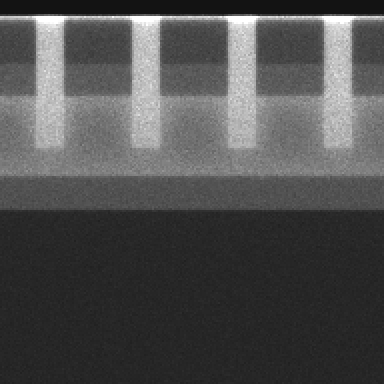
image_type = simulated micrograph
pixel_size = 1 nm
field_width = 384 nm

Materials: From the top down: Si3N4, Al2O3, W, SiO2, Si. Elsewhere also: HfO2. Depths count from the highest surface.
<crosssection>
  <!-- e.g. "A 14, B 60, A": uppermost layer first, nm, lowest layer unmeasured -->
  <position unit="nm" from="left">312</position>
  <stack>Si3N4 48, Al2O3 32, W 80, SiO2 34, Si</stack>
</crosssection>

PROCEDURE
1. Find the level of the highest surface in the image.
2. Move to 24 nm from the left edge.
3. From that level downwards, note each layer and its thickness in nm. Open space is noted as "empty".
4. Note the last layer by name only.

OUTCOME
Si3N4 48, Al2O3 32, W 80, SiO2 34, Si